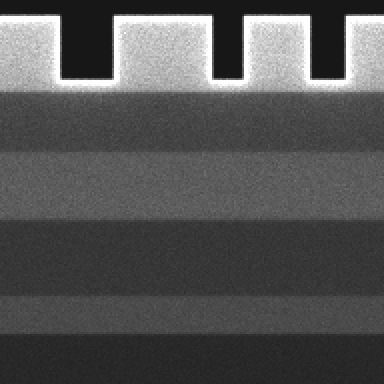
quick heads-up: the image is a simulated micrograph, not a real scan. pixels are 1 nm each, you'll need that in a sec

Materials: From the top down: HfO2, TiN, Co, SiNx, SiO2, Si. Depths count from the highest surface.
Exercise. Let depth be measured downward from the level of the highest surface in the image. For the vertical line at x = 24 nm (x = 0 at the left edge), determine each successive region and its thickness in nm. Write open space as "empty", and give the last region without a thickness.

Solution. HfO2 76, TiN 60, Co 68, SiNx 76, SiO2 38, Si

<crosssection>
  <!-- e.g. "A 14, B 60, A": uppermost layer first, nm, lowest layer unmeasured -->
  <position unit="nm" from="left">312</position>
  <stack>empty 64, HfO2 12, TiN 60, Co 68, SiNx 76, SiO2 38, Si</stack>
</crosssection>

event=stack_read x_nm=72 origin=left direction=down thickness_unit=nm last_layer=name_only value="empty 64, HfO2 12, TiN 60, Co 68, SiNx 76, SiO2 38, Si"